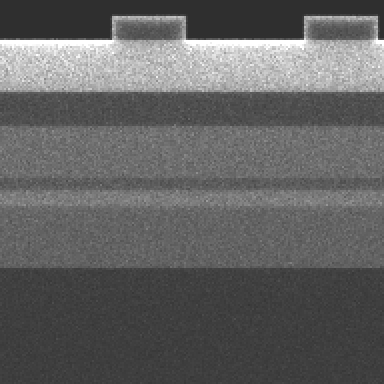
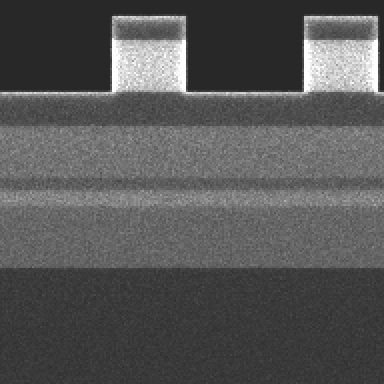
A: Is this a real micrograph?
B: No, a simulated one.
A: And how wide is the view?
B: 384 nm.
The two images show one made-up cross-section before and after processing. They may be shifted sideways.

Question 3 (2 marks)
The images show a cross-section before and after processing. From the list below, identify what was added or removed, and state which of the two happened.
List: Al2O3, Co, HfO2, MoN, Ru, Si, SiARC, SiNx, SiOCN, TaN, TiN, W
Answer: HfO2 was removed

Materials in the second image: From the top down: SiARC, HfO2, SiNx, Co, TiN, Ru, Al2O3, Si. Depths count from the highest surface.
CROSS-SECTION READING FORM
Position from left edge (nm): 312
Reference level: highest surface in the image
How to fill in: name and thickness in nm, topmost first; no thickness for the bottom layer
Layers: SiARC 24, HfO2 52, SiNx 34, Co 52, TiN 12, Ru 16, Al2O3 62, Si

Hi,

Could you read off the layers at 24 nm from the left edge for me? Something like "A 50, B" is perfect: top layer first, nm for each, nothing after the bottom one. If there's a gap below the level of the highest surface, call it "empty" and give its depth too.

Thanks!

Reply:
empty 76, SiNx 34, Co 52, TiN 12, Ru 16, Al2O3 62, Si